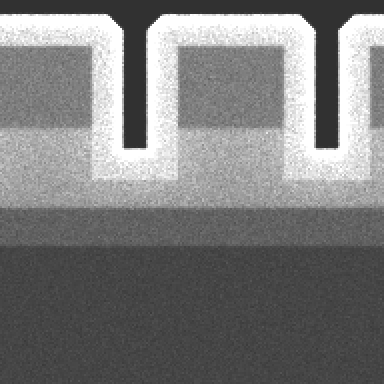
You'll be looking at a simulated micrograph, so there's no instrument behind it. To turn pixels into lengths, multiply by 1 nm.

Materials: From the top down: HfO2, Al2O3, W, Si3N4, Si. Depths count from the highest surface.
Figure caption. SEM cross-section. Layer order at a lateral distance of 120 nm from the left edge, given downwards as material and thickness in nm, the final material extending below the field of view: empty 14, HfO2 150, W 28, Si3N4 38, Si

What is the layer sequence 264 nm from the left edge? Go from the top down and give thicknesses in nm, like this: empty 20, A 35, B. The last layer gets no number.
HfO2 30, Al2O3 82, W 80, Si3N4 38, Si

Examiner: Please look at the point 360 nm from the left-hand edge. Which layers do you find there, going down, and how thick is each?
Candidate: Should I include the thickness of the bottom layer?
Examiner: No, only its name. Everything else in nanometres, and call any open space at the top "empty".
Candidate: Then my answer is HfO2 164, W 28, Si3N4 38, Si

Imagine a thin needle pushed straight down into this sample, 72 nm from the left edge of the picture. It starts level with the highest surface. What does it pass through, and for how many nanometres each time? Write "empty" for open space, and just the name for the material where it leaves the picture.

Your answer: HfO2 30, Al2O3 82, W 80, Si3N4 38, Si